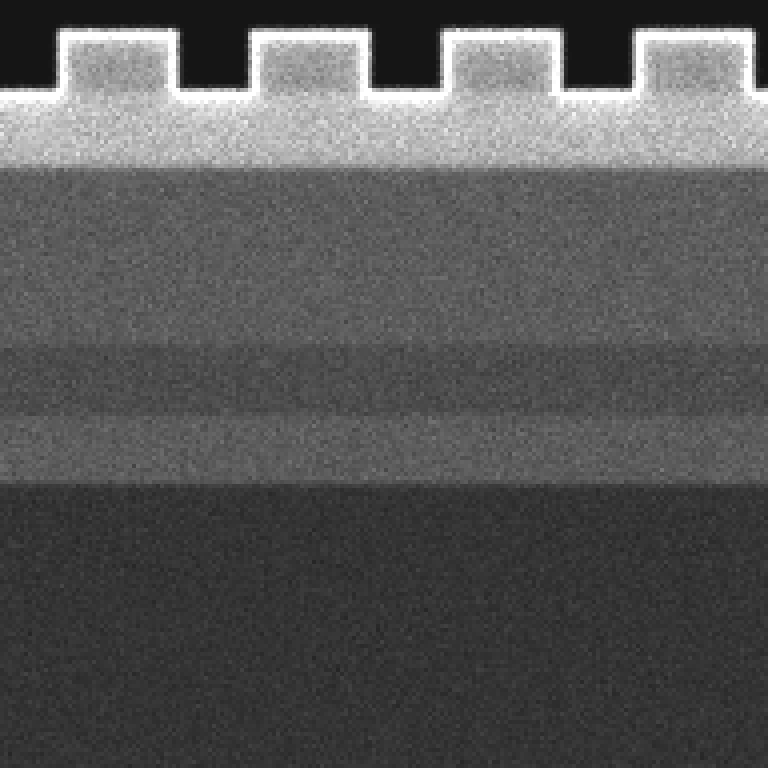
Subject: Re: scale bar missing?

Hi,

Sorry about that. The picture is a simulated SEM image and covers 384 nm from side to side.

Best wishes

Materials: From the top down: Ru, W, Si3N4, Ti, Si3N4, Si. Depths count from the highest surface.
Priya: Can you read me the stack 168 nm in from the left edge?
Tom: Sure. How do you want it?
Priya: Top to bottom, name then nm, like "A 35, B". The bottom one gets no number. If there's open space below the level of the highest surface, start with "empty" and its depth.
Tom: Ru 30, W 38, Si3N4 88, Ti 36, Si3N4 34, Si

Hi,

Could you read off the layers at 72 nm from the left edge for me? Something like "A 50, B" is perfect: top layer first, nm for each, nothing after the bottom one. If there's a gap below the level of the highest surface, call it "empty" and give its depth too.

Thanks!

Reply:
Ru 30, W 38, Si3N4 88, Ti 36, Si3N4 34, Si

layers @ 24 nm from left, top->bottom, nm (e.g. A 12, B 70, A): empty 30, W 38, Si3N4 88, Ti 36, Si3N4 34, Si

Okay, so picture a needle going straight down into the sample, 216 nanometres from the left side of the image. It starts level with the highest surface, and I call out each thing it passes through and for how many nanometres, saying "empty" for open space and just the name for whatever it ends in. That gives empty 30, W 38, Si3N4 88, Ti 36, Si3N4 34, Si